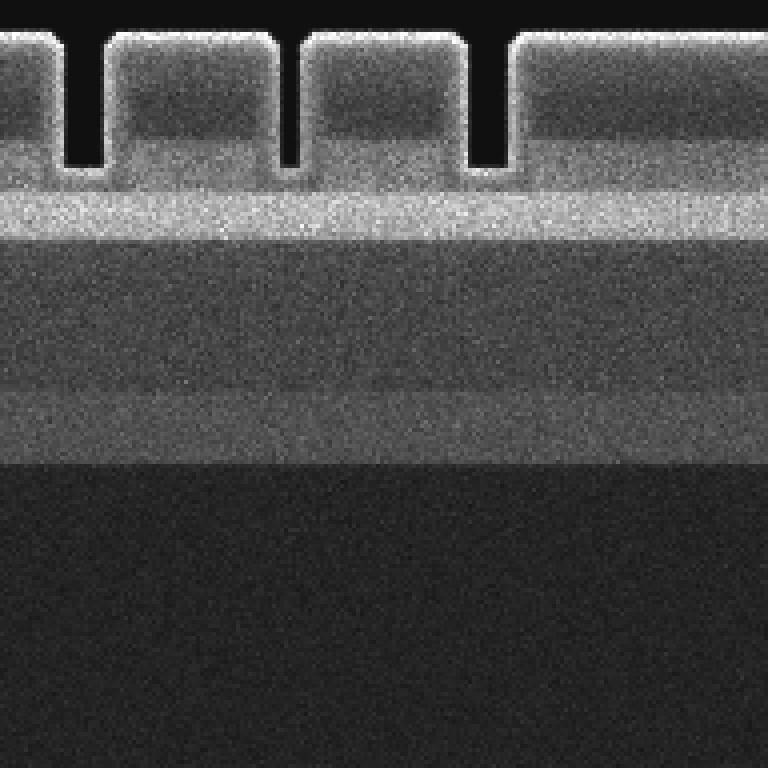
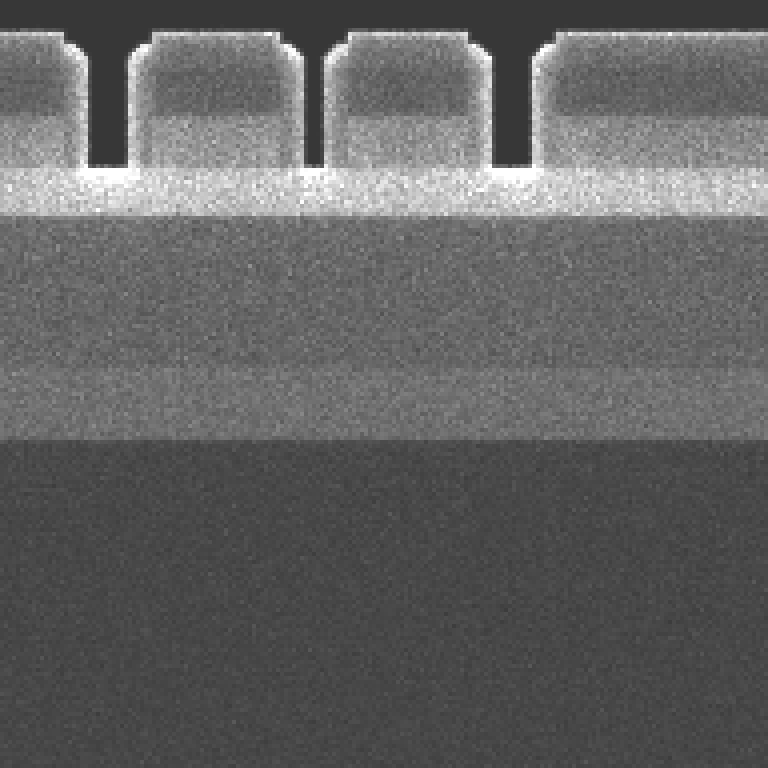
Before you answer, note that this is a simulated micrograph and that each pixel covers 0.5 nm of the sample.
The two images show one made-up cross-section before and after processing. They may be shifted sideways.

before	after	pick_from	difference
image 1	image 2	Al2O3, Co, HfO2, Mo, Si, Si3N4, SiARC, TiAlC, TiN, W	Al2O3 removed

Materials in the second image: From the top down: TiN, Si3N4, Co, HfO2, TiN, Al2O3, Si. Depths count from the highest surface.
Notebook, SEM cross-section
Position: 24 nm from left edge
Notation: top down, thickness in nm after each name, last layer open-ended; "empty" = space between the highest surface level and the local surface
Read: TiN 18, Si3N4 24, Co 26, HfO2 24, TiN 76, Al2O3 36, Si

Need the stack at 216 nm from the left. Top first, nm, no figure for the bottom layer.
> TiN 18, Si3N4 24, Co 26, HfO2 24, TiN 76, Al2O3 36, Si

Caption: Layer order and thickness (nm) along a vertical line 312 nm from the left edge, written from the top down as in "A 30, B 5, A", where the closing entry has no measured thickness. TiN 18, Si3N4 24, Co 26, HfO2 24, TiN 76, Al2O3 36, Si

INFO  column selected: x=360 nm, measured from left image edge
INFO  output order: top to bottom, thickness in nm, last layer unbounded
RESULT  TiN 18, Si3N4 24, Co 26, HfO2 24, TiN 76, Al2O3 36, Si